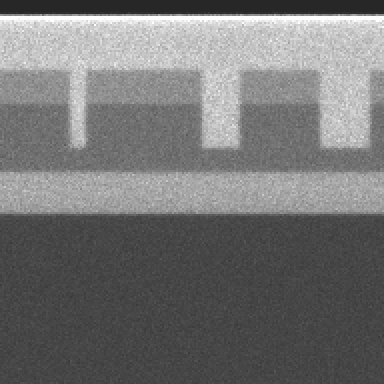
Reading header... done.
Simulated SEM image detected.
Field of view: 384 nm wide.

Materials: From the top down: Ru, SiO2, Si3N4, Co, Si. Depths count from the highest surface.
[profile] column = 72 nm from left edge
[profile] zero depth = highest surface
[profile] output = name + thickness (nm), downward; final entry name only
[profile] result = Ru 132, Si3N4 24, Co 42, Si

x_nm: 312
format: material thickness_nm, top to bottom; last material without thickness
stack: Ru 54, SiO2 34, Si3N4 68, Co 42, Si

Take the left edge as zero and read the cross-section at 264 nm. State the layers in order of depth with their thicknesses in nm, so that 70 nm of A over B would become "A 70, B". Ru 54, SiO2 34, Si3N4 68, Co 42, Si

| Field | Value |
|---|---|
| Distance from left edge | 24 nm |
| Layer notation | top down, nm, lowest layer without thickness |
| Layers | Ru 54, SiO2 34, Si3N4 68, Co 42, Si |